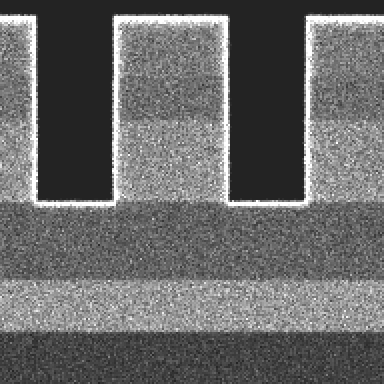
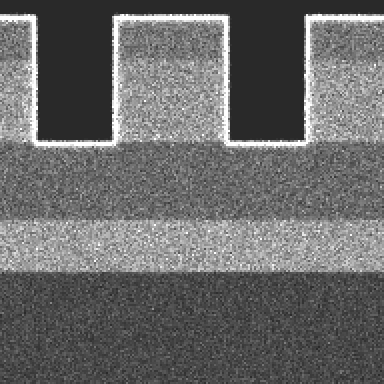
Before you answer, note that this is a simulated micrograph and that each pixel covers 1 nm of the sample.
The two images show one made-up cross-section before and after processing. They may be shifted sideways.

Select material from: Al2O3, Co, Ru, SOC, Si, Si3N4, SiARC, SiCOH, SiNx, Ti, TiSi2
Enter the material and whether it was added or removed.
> SOC / removed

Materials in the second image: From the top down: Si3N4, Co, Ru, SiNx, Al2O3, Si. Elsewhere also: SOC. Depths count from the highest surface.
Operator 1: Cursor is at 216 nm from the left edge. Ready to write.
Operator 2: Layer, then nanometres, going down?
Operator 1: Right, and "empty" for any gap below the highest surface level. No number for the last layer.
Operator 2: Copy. Si3N4 44, Co 72, Ru 10, SiNx 78, Al2O3 52, Si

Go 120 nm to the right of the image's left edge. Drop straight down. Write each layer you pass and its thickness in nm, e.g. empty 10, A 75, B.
Si3N4 44, Co 72, Ru 10, SiNx 78, Al2O3 52, Si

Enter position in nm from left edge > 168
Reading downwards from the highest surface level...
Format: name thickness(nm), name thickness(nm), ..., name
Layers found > Si3N4 44, Co 72, Ru 10, SiNx 78, Al2O3 52, Si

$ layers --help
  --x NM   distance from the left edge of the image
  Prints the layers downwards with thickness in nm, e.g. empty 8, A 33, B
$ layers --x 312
Si3N4 44, Co 72, Ru 10, SiNx 78, Al2O3 52, Si